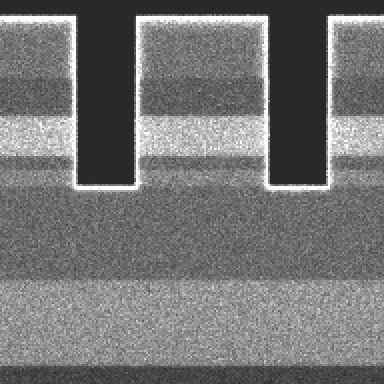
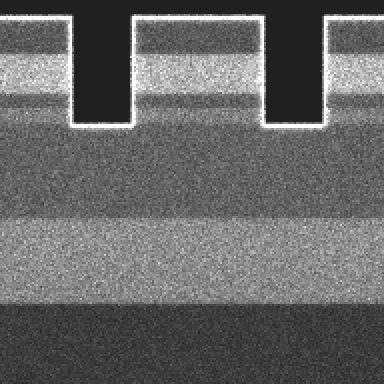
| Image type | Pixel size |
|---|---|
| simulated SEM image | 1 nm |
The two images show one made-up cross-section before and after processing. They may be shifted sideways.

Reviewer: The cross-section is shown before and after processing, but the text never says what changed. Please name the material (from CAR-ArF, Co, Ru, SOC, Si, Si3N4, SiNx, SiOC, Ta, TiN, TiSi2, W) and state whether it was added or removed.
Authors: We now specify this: SOC, removed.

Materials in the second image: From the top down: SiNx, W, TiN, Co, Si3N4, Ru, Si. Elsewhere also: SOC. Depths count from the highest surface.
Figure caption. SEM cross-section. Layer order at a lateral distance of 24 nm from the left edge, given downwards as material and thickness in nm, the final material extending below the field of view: SiNx 38, W 40, TiN 14, Co 16, Si3N4 94, Ru 86, Si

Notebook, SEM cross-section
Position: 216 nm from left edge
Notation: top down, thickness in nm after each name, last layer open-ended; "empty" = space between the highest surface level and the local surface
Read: SiNx 38, W 40, TiN 14, Co 16, Si3N4 94, Ru 86, Si